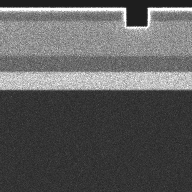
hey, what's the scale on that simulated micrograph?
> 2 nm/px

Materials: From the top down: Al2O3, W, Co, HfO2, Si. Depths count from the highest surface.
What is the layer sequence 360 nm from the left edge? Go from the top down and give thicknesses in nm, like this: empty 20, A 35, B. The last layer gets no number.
Al2O3 26, W 70, Co 32, HfO2 36, Si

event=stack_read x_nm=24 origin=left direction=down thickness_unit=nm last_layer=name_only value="Al2O3 26, W 70, Co 32, HfO2 36, Si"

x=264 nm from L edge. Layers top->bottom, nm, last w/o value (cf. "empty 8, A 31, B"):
empty 38, W 58, Co 32, HfO2 36, Si